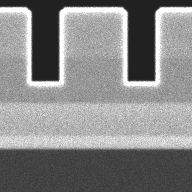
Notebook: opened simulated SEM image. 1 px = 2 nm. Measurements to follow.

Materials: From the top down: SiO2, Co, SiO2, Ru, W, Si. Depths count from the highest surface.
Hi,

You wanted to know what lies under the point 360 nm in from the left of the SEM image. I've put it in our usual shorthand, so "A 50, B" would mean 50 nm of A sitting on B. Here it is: SiO2 12, Co 88, SiO2 90, Ru 66, W 26, Si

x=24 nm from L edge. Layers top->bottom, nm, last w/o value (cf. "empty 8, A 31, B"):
SiO2 12, Co 88, SiO2 90, Ru 66, W 26, Si